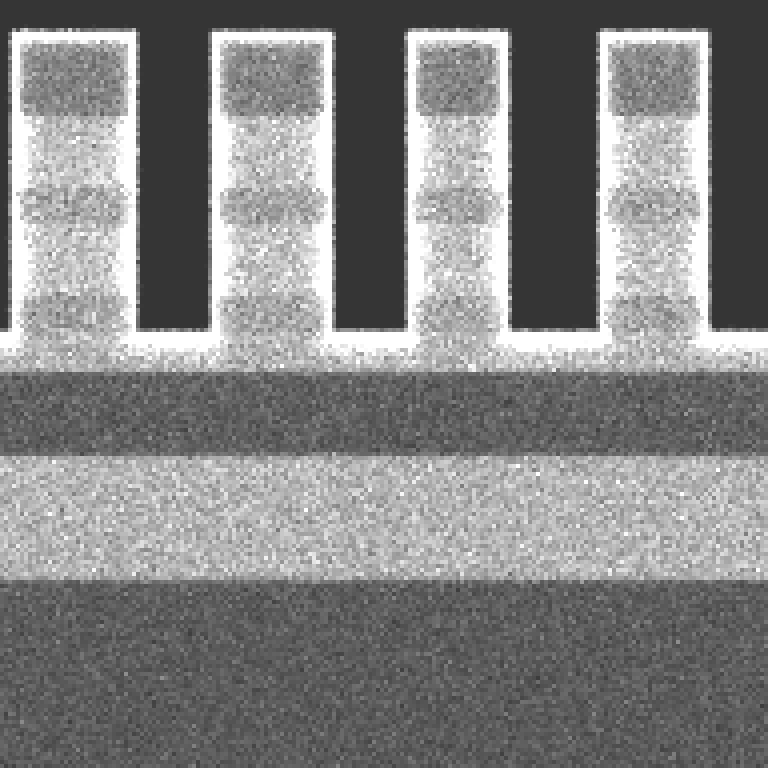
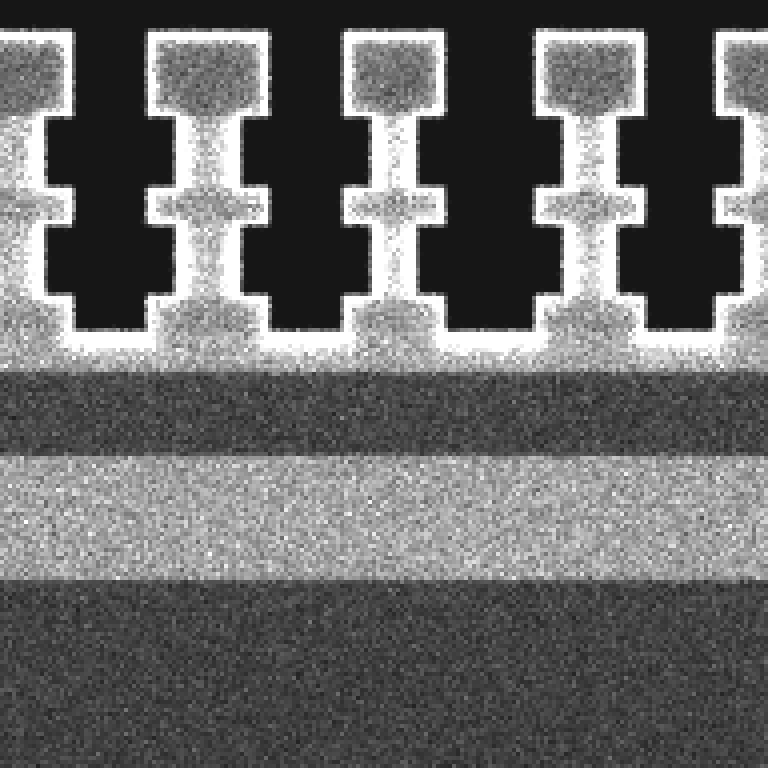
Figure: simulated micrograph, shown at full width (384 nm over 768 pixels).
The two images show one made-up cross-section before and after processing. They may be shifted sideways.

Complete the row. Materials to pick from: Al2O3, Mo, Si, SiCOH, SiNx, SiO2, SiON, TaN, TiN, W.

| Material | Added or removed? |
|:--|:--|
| Al2O3 | removed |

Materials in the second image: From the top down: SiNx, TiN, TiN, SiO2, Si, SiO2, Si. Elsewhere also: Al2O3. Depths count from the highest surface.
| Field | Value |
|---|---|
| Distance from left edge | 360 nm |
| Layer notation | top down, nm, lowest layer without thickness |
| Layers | SiNx 42, empty 36, TiN 18, empty 36, TiN 18, SiO2 20, Si 42, SiO2 62, Si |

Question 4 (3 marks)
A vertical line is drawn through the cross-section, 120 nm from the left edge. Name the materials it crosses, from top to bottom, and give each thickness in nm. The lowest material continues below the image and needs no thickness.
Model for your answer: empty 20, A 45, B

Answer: SiNx 42, empty 36, TiN 18, empty 36, TiN 18, SiO2 20, Si 42, SiO2 62, Si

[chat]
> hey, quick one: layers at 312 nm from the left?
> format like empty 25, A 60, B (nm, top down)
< SiNx 42, empty 36, TiN 18, empty 36, TiN 18, SiO2 20, Si 42, SiO2 62, Si